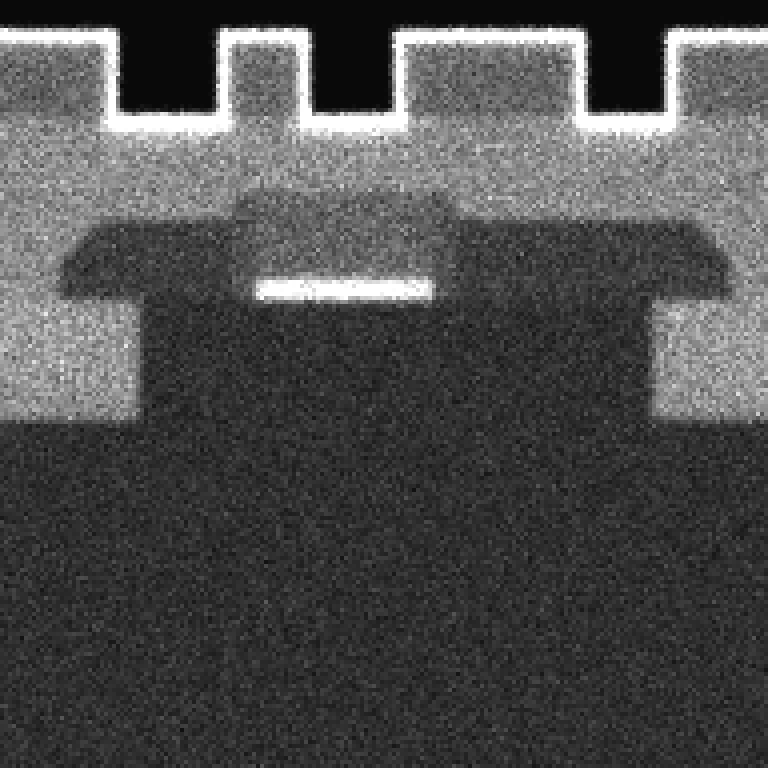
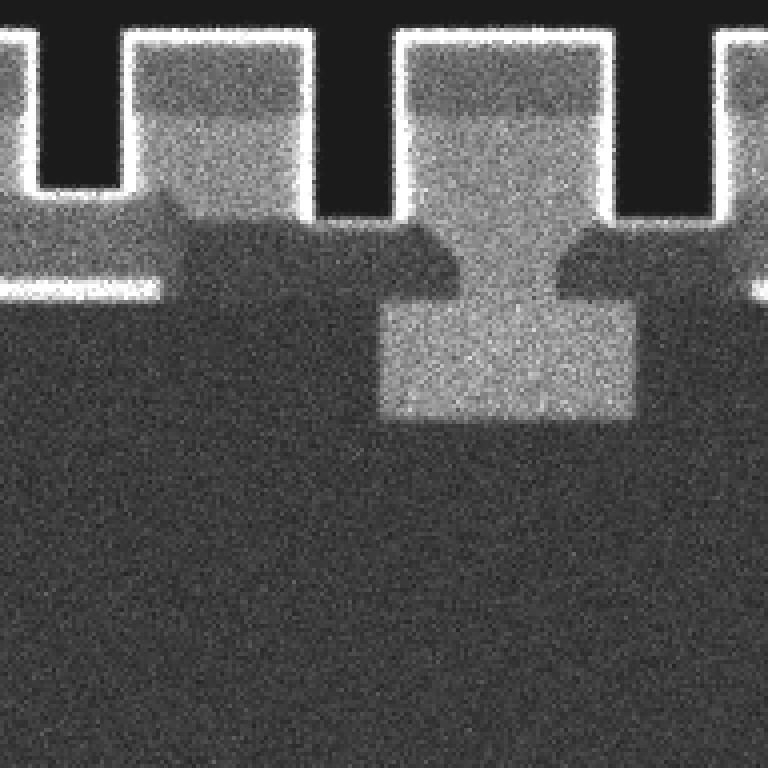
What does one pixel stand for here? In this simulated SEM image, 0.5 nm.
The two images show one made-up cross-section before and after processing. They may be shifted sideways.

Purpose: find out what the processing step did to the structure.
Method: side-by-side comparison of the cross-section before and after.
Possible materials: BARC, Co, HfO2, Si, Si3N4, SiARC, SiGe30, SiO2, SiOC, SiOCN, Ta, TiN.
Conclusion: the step removed SiO2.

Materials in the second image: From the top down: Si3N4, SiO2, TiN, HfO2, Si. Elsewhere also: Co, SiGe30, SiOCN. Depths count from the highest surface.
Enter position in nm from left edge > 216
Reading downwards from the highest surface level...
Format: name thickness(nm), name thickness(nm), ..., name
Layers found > Si3N4 42, SiO2 60, SiGe30 32, Co 60, Si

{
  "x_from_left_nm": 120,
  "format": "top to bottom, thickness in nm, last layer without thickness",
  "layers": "Si3N4 42, SiO2 52, SiGe30 40, Si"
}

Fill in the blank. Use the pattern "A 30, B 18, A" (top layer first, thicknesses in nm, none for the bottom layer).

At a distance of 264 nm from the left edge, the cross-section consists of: Si3N4 42, SiO2 92, Co 60, Si